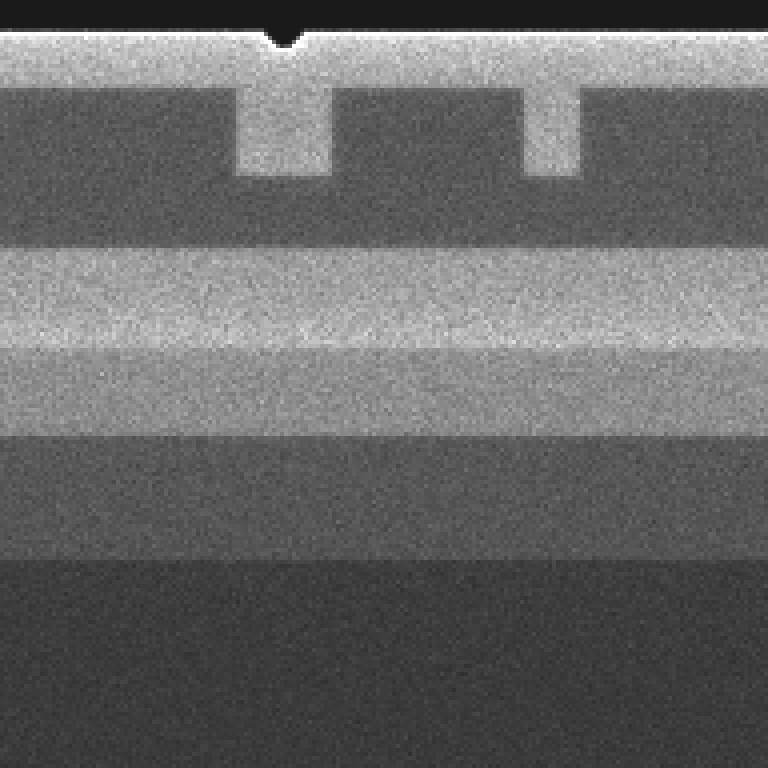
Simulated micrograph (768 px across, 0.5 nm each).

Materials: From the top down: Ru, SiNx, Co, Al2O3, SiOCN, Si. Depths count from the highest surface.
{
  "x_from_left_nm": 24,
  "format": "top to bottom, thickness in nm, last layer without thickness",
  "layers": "Ru 28, SiNx 80, Co 50, Al2O3 44, SiOCN 62, Si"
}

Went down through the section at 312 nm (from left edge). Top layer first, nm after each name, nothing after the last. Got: Ru 28, SiNx 80, Co 50, Al2O3 44, SiOCN 62, Si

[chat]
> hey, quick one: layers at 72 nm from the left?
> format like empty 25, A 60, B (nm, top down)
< Ru 28, SiNx 80, Co 50, Al2O3 44, SiOCN 62, Si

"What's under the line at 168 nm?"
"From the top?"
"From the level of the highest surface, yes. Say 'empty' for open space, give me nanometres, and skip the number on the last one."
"Ru 28, SiNx 80, Co 50, Al2O3 44, SiOCN 62, Si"